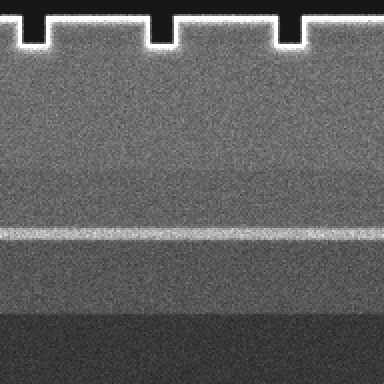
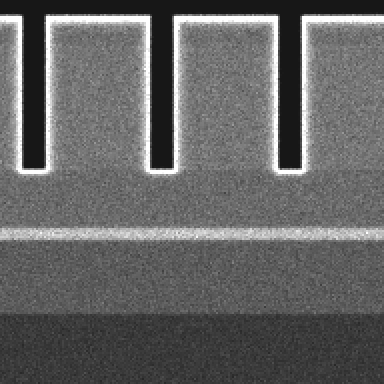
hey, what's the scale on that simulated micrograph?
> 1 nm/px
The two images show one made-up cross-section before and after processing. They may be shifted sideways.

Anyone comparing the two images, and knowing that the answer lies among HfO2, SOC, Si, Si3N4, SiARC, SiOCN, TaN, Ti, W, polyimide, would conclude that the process removed SOC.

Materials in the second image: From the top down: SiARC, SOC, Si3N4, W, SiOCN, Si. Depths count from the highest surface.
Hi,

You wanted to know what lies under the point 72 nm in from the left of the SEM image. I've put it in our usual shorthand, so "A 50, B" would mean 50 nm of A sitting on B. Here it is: SiARC 28, SOC 126, Si3N4 58, W 12, SiOCN 74, Si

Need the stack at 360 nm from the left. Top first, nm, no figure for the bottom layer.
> SiARC 28, SOC 126, Si3N4 58, W 12, SiOCN 74, Si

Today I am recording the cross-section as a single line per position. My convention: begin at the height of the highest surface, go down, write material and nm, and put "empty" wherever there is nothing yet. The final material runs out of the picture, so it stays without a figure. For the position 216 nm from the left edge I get SiARC 28, SOC 126, Si3N4 58, W 12, SiOCN 74, Si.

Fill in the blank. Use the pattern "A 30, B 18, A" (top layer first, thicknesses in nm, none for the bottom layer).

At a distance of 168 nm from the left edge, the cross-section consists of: empty 154, Si3N4 58, W 12, SiOCN 74, Si